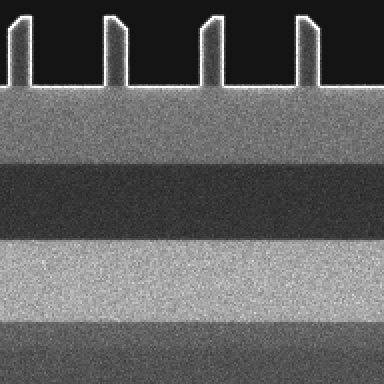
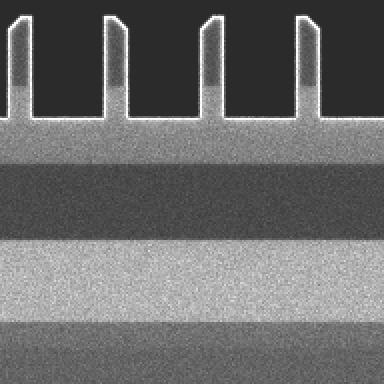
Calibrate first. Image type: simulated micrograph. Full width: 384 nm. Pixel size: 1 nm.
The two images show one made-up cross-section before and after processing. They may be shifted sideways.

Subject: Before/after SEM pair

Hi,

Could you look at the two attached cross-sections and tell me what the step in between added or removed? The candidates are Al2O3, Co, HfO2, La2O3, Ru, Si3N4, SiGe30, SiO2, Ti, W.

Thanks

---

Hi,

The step removed W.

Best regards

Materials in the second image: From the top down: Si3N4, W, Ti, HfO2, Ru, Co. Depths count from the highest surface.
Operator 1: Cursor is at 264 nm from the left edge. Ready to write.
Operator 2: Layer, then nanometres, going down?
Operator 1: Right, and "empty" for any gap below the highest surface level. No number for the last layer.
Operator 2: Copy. empty 102, W 46, Ti 76, HfO2 82, Ru 26, Co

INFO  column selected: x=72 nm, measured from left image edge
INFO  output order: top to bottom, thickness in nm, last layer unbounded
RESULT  empty 102, W 46, Ti 76, HfO2 82, Ru 26, Co